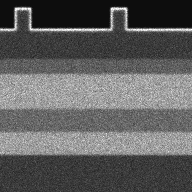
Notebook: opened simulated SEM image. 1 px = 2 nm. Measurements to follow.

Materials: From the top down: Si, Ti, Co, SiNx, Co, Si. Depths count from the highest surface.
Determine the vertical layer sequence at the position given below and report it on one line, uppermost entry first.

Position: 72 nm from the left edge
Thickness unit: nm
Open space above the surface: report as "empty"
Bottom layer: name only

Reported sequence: empty 42, Si 60, Ti 30, Co 70, SiNx 46, Co 46, Si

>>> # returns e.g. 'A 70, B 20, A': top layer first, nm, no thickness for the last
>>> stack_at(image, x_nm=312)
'empty 42, Si 60, Ti 30, Co 70, SiNx 46, Co 46, Si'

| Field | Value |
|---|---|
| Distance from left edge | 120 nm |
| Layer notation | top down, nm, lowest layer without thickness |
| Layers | empty 42, Si 60, Ti 30, Co 70, SiNx 46, Co 46, Si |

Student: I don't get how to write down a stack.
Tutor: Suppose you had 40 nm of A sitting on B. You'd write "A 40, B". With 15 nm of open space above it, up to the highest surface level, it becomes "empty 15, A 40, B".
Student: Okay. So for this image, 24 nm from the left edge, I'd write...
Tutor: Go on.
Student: empty 42, Si 60, Ti 30, Co 70, SiNx 46, Co 46, Si